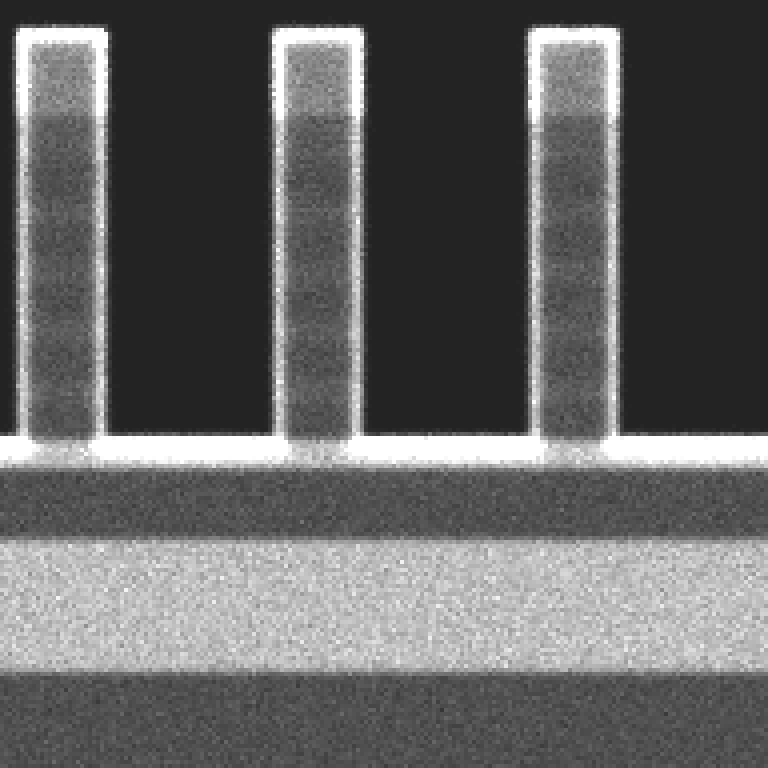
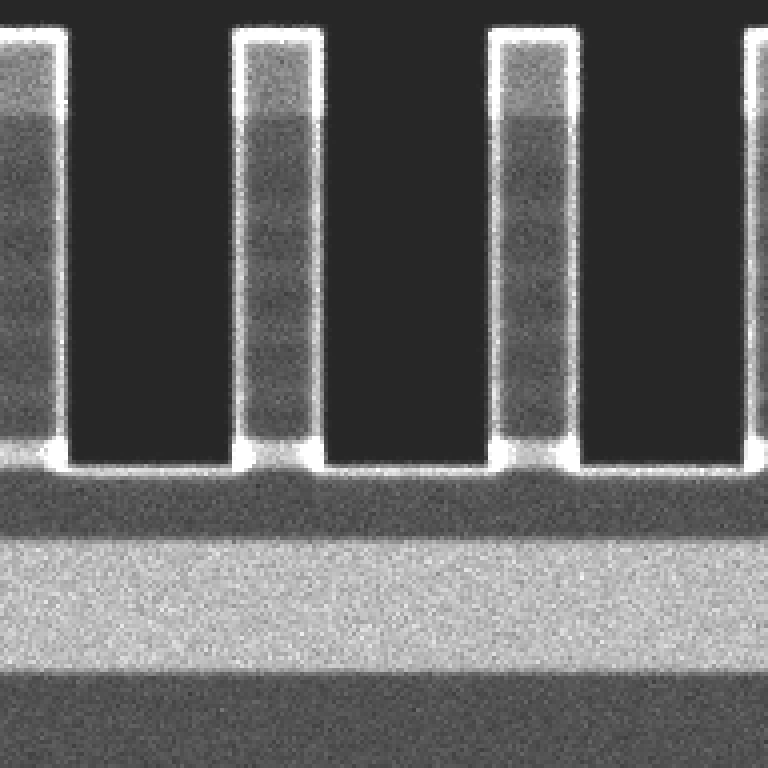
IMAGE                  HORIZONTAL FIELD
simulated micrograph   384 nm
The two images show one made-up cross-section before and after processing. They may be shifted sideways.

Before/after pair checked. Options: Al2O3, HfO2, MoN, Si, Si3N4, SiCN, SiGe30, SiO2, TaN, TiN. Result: removed Al2O3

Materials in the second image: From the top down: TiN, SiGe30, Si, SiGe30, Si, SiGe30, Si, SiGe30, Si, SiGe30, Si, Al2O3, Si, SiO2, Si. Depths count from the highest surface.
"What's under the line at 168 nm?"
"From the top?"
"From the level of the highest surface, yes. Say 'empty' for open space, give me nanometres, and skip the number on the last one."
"empty 218, Si 36, SiO2 66, Si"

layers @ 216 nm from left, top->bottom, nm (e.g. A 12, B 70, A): empty 218, Si 36, SiO2 66, Si